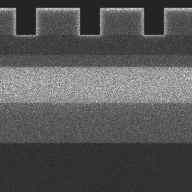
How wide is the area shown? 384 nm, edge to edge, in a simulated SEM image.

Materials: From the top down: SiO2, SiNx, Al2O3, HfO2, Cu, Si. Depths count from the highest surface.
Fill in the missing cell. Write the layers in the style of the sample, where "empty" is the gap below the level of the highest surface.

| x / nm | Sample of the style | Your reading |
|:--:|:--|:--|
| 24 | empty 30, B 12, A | SiO2 54, SiNx 40, Al2O3 24, HfO2 72, Cu 80, Si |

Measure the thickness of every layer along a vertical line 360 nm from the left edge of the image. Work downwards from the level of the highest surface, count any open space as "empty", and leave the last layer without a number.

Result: SiO2 54, SiNx 40, Al2O3 24, HfO2 72, Cu 80, Si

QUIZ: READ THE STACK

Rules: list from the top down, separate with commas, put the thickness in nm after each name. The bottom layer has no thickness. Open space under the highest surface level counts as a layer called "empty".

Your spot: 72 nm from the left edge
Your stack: SiO2 54, SiNx 40, Al2O3 24, HfO2 72, Cu 80, Si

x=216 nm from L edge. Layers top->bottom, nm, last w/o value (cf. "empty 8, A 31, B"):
SiO2 54, SiNx 40, Al2O3 24, HfO2 72, Cu 80, Si